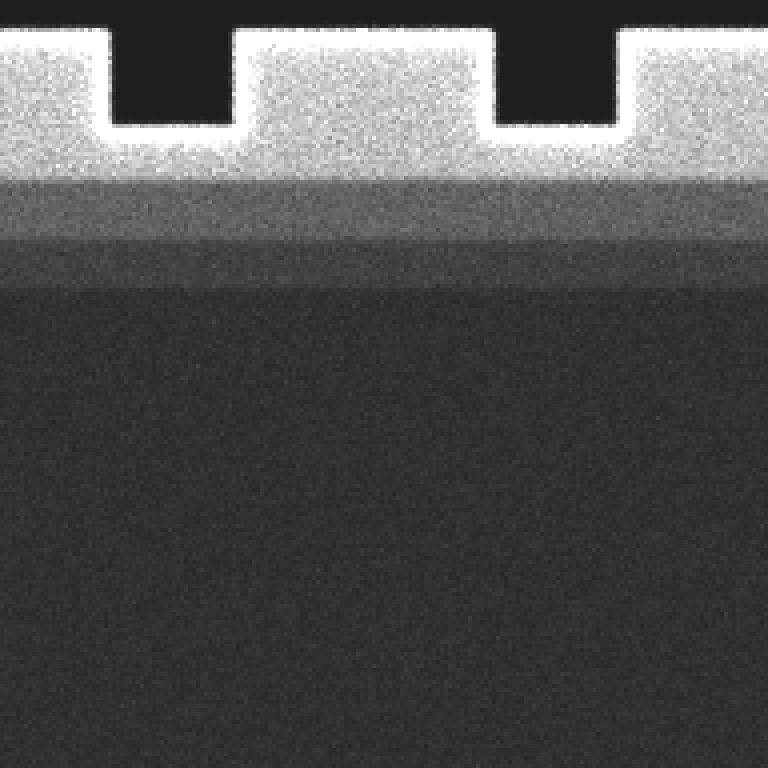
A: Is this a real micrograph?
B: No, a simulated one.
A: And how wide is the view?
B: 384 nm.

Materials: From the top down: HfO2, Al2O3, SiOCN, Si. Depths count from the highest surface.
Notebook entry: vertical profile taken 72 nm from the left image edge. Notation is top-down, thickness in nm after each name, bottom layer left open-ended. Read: empty 48, HfO2 26, Al2O3 30, SiOCN 24, Si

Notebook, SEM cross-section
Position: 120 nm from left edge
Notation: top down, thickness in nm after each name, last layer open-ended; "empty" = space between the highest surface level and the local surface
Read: HfO2 74, Al2O3 30, SiOCN 24, Si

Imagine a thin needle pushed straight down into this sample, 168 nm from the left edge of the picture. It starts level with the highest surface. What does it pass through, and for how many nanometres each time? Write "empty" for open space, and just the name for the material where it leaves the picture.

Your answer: HfO2 74, Al2O3 30, SiOCN 24, Si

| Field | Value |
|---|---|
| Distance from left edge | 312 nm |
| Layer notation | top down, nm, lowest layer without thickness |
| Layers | HfO2 74, Al2O3 30, SiOCN 24, Si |